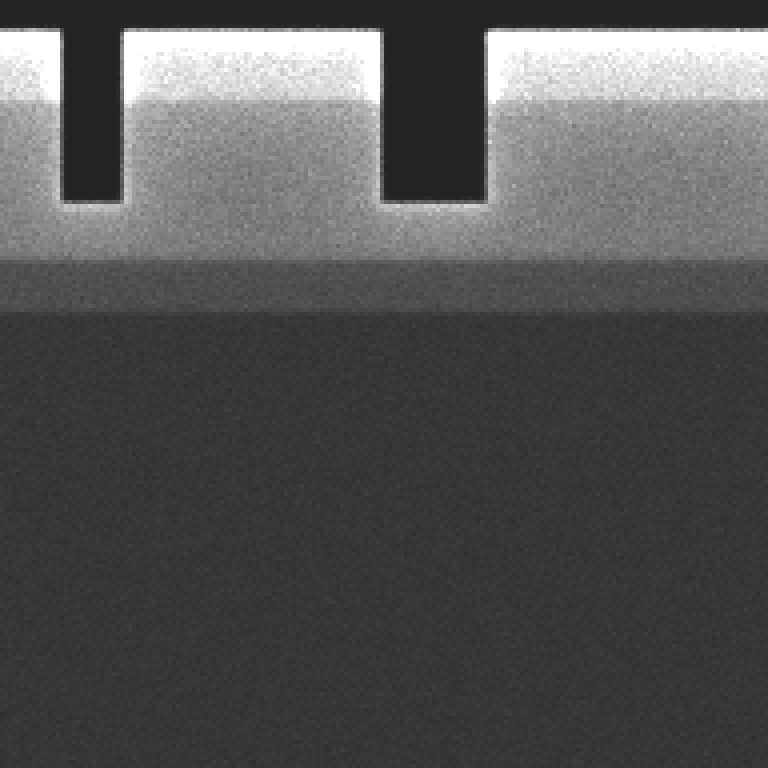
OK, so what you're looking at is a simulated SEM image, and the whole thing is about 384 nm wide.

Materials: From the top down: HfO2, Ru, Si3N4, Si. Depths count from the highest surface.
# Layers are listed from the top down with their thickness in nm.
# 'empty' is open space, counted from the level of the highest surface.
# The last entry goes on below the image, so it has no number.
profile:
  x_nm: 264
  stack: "HfO2 34, Ru 80, Si3N4 26, Si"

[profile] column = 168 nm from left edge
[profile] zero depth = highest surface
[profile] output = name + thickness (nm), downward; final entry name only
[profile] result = HfO2 34, Ru 80, Si3N4 26, Si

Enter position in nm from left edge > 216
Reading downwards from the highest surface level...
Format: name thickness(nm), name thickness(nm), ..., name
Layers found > empty 86, Ru 28, Si3N4 26, Si